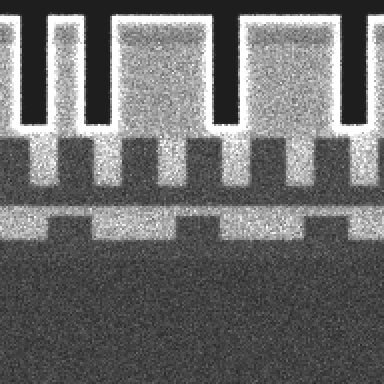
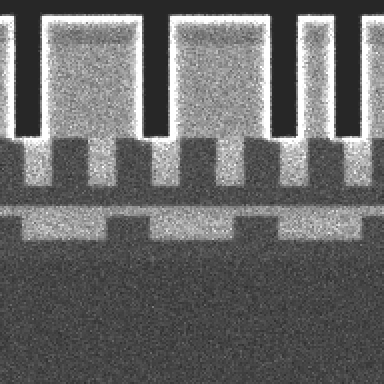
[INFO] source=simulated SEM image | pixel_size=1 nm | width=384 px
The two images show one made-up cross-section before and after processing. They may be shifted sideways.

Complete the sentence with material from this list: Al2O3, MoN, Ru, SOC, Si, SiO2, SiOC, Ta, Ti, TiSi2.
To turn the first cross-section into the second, Al2O3 must be removed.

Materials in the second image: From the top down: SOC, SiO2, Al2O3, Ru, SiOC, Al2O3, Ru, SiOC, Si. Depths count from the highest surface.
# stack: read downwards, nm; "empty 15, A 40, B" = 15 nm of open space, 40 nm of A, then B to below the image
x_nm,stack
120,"SOC 28, SiO2 82, Al2O3 12, SiOC 68, Al2O3 10, SiOC 44, Si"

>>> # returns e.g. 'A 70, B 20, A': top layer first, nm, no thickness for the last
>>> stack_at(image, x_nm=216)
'SOC 28, SiO2 82, Al2O3 12, Ru 48, SiOC 20, Al2O3 10, Ru 24, SiOC 20, Si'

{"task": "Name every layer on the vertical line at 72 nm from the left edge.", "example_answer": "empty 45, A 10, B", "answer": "SOC 28, SiO2 82, Al2O3 12, SiOC 68, Al2O3 10, Ru 24, SiOC 20, Si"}